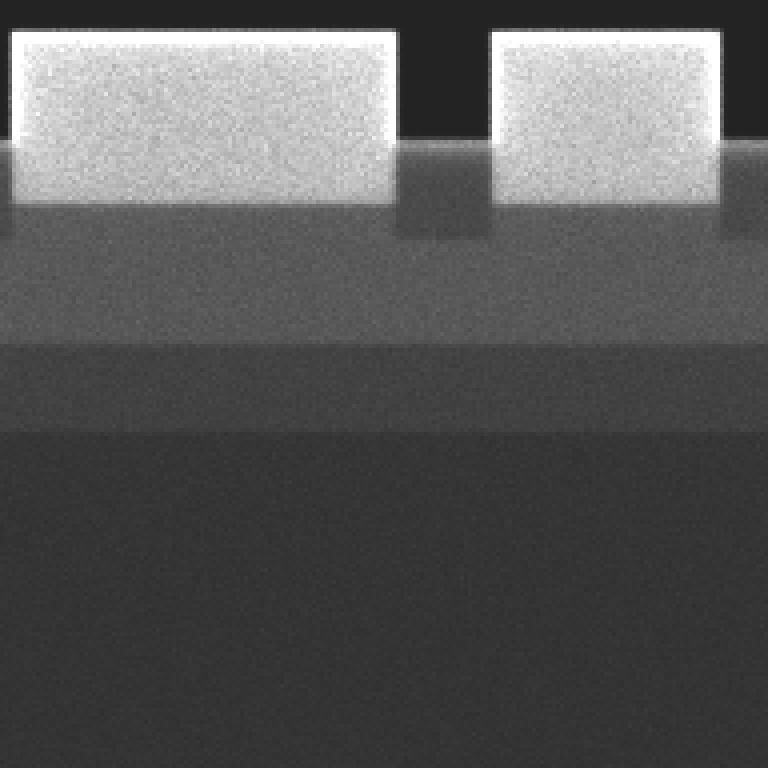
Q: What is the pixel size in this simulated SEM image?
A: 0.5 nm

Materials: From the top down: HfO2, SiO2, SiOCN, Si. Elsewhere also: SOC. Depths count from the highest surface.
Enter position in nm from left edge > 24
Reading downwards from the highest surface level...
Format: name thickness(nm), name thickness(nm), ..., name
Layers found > HfO2 86, SiO2 70, SiOCN 44, Si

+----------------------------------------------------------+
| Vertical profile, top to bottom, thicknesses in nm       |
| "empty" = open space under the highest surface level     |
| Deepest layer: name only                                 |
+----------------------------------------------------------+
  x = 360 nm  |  empty 54, SOC 50, SiO2 52, SiOCN 44, Si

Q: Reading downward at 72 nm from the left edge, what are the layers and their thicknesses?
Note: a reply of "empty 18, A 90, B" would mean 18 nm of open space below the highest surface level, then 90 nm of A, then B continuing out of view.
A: HfO2 86, SiO2 70, SiOCN 44, Si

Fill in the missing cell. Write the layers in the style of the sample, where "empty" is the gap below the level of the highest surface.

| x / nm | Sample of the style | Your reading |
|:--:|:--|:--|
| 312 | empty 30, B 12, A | HfO2 86, SiO2 70, SiOCN 44, Si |